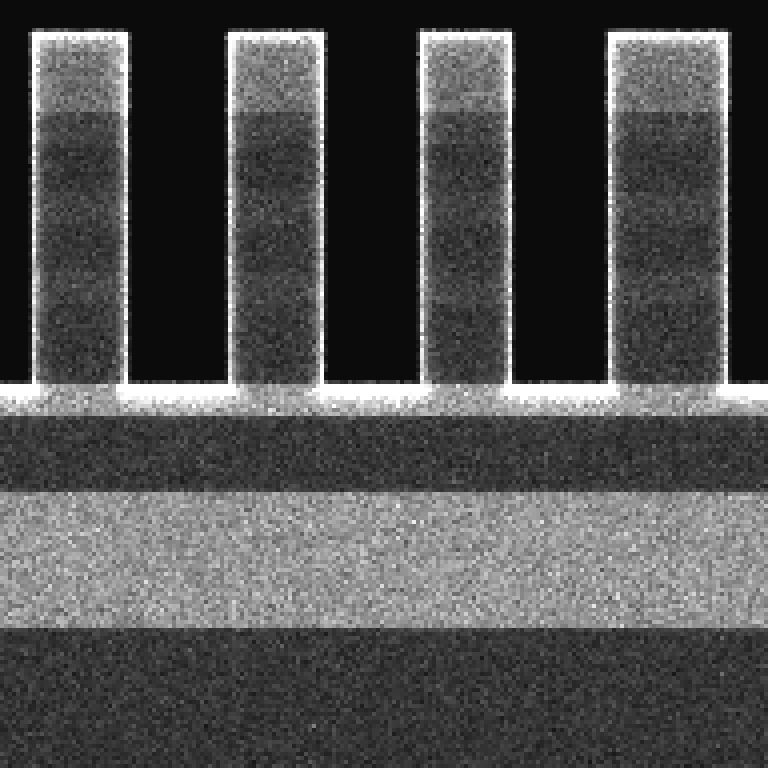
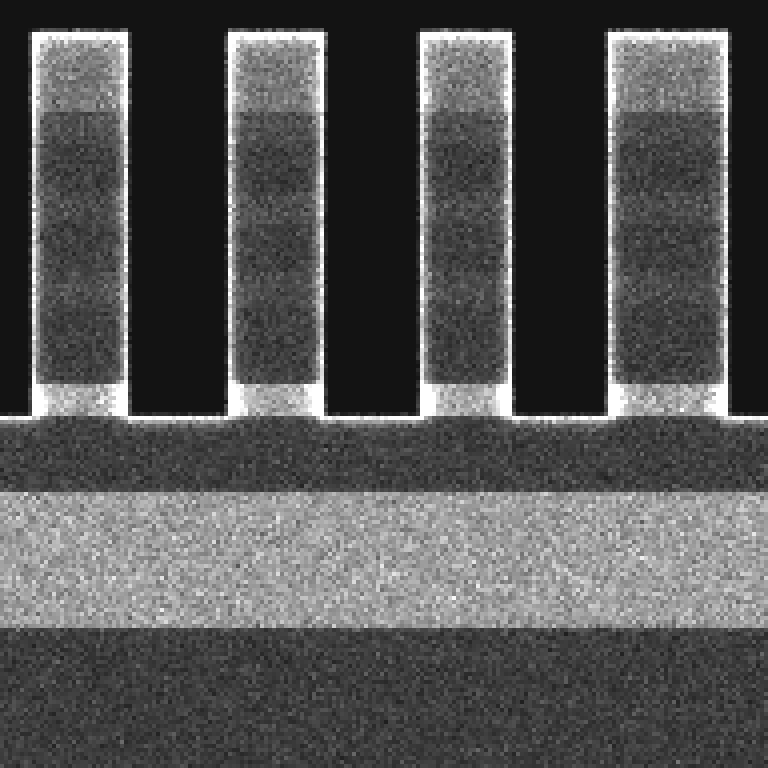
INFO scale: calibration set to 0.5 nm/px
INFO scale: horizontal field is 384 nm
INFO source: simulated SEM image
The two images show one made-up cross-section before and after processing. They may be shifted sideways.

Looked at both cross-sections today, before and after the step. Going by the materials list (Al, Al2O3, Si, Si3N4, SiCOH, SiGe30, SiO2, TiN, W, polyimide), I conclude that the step removed Al2O3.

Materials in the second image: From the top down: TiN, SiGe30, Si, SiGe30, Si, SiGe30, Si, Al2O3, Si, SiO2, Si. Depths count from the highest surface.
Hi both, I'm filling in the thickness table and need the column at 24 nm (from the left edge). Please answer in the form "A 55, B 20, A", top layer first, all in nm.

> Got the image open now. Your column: TiN 40, SiGe30 16, Si 24, SiGe30 16, Si 24, SiGe30 16, Si 40, Al2O3 16, Si 38, SiO2 68, Si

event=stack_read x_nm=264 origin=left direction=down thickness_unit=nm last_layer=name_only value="empty 192, Si 38, SiO2 68, Si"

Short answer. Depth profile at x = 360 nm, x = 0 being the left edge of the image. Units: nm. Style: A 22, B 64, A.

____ TiN 40, SiGe30 16, Si 24, SiGe30 16, Si 24, SiGe30 16, Si 40, Al2O3 16, Si 38, SiO2 68, Si